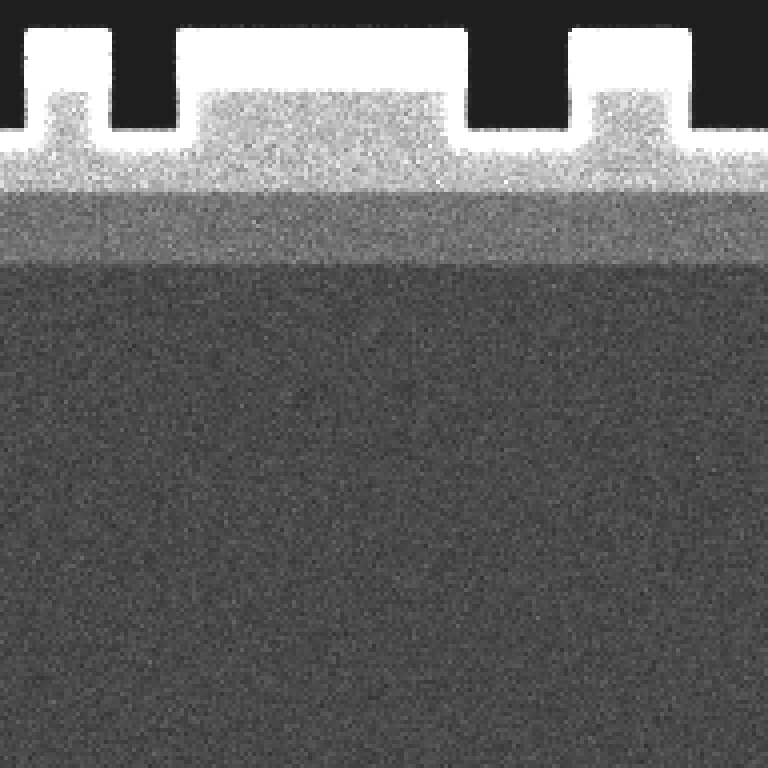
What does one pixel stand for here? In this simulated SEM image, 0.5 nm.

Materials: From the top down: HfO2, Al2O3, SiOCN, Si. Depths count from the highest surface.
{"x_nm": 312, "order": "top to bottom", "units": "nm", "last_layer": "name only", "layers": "HfO2 28, Al2O3 52, SiOCN 36, Si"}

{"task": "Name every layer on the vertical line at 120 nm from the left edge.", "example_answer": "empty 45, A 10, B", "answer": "HfO2 28, Al2O3 52, SiOCN 36, Si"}